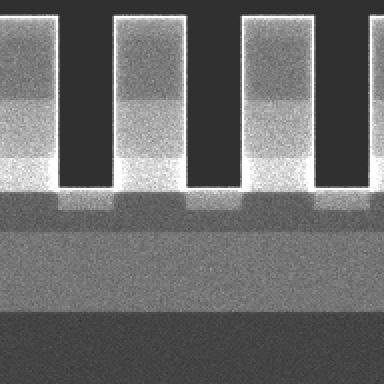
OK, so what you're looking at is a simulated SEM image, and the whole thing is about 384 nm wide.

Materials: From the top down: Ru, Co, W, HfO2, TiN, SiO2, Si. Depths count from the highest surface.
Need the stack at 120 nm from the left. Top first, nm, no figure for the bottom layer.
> Ru 22, Co 62, W 58, HfO2 34, TiN 40, SiO2 80, Si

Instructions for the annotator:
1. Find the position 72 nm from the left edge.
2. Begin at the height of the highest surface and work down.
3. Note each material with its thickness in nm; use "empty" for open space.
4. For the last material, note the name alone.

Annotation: empty 172, Ru 22, TiN 22, SiO2 80, Si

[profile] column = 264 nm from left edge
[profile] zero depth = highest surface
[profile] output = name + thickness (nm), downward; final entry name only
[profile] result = Ru 22, Co 62, W 58, HfO2 34, TiN 40, SiO2 80, Si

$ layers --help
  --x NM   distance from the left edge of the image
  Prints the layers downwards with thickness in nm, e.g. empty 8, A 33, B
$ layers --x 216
empty 172, Ru 22, TiN 22, SiO2 80, Si